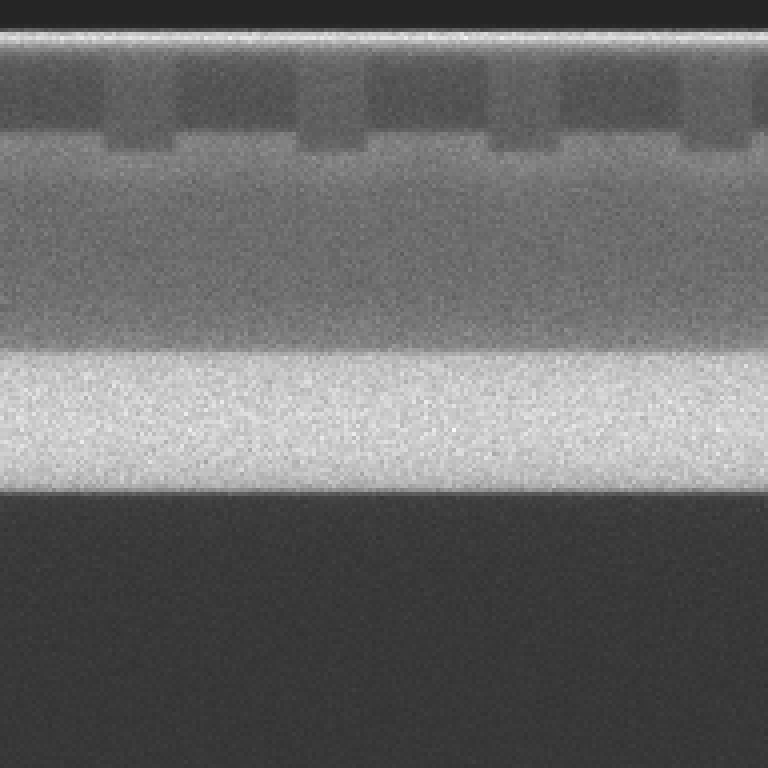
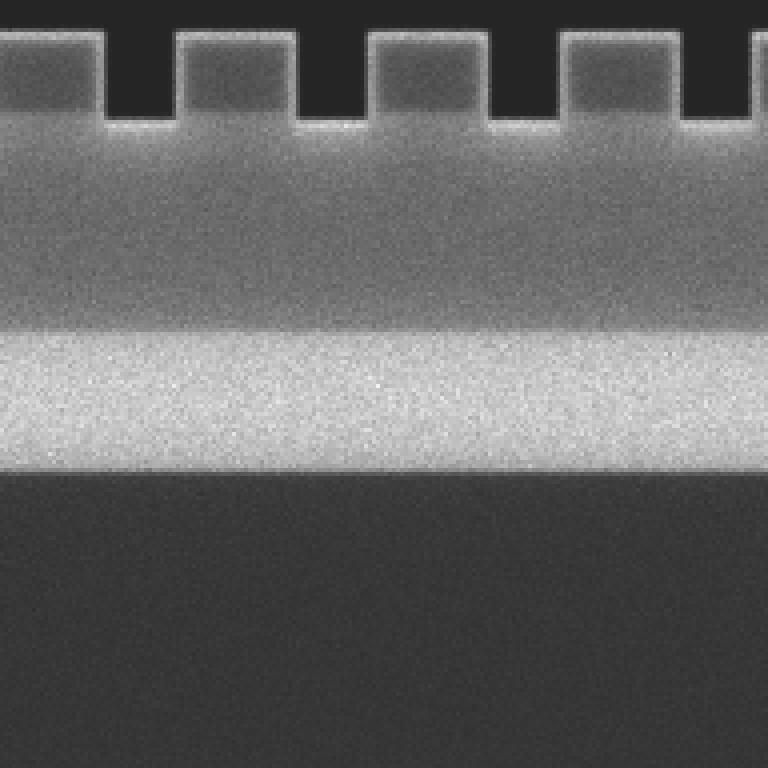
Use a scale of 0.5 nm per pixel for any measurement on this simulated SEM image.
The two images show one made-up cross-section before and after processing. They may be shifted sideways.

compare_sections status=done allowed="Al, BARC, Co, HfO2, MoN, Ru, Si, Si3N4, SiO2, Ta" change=removed material="SiO2"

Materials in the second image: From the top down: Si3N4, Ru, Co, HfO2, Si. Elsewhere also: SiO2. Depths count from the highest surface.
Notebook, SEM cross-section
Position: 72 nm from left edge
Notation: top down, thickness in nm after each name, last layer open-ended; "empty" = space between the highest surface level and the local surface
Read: empty 44, SiO2 6, Ru 14, Co 86, HfO2 70, Si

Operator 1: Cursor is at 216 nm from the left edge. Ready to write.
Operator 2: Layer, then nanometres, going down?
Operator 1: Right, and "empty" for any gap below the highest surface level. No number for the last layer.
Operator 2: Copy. Si3N4 40, Ru 24, Co 86, HfO2 70, Si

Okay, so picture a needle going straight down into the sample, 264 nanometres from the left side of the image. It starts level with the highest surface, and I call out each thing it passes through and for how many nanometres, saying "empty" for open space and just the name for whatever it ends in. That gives empty 44, SiO2 6, Ru 14, Co 86, HfO2 70, Si